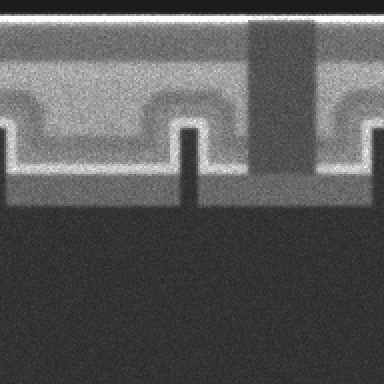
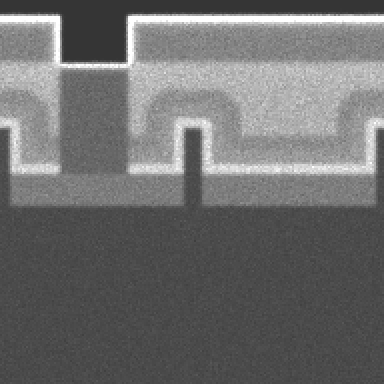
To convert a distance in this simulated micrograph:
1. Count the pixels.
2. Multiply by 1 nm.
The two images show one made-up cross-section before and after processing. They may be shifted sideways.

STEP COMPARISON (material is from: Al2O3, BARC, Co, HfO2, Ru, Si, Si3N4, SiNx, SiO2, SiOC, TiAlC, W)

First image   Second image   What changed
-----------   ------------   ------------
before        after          Si3N4, removed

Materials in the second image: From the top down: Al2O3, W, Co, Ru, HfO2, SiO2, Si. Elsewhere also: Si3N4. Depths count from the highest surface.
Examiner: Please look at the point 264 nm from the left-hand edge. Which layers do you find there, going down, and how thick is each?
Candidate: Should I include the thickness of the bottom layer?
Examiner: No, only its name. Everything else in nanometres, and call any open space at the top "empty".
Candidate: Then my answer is Al2O3 46, W 74, Co 14, Ru 14, HfO2 10, SiO2 32, Si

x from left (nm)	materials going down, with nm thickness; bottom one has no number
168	Al2O3 46, W 28, Co 16, Ru 58, HfO2 10, SiO2 32, Si